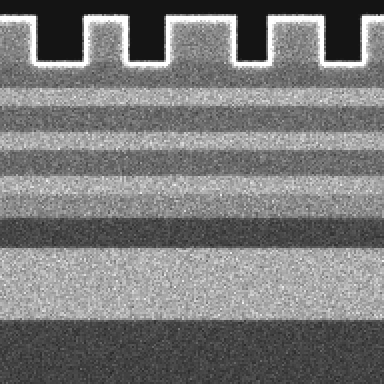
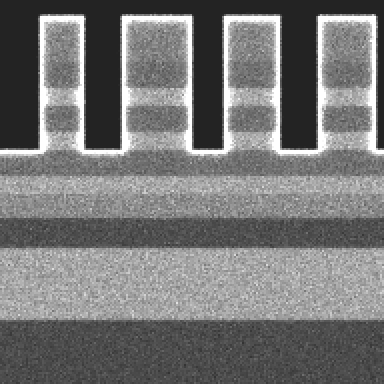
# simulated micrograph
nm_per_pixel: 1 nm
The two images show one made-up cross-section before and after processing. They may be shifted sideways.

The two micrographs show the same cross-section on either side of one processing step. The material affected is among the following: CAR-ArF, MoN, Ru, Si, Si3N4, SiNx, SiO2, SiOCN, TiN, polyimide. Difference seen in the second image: SiO2 and SiOCN removed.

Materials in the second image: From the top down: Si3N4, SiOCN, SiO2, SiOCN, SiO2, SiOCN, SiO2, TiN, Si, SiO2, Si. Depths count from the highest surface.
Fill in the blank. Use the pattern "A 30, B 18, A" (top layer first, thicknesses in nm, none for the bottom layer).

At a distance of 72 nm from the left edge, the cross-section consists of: Si3N4 46, SiOCN 26, SiO2 18, SiOCN 26, SiO2 18, SiOCN 26, SiO2 18, TiN 24, Si 30, SiO2 72, Si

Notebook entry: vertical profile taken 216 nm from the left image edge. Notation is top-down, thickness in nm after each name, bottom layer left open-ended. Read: empty 134, SiOCN 26, SiO2 18, TiN 24, Si 30, SiO2 72, Si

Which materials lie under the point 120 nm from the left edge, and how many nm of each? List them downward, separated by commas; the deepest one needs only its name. empty 134, SiOCN 26, SiO2 18, TiN 24, Si 30, SiO2 72, Si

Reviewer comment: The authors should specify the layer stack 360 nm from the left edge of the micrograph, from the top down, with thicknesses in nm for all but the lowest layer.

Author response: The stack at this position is Si3N4 46, SiOCN 26, SiO2 18, SiOCN 26, SiO2 18, SiOCN 26, SiO2 18, TiN 24, Si 30, SiO2 72, Si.